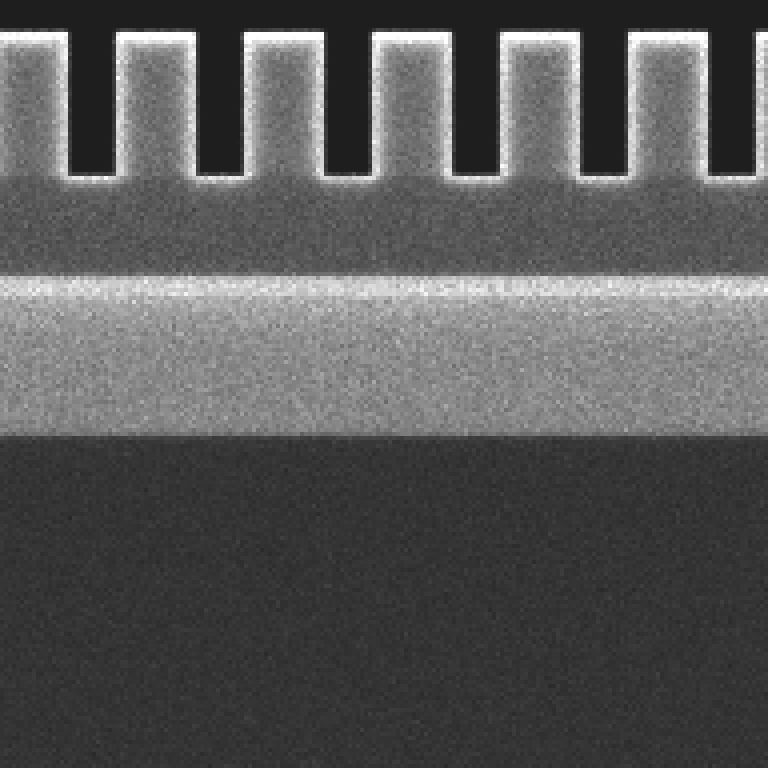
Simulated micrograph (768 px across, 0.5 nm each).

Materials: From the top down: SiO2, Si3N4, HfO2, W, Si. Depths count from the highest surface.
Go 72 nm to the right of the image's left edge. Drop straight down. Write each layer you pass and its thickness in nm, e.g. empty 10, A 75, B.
SiO2 72, Si3N4 50, HfO2 10, W 70, Si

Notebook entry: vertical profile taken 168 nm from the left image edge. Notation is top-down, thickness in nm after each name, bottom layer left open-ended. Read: empty 72, Si3N4 50, HfO2 10, W 70, Si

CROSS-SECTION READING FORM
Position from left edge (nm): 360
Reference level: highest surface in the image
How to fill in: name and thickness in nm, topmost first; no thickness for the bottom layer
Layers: empty 72, Si3N4 50, HfO2 10, W 70, Si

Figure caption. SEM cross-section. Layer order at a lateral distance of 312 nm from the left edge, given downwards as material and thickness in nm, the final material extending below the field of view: empty 72, Si3N4 50, HfO2 10, W 70, Si